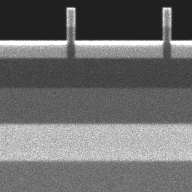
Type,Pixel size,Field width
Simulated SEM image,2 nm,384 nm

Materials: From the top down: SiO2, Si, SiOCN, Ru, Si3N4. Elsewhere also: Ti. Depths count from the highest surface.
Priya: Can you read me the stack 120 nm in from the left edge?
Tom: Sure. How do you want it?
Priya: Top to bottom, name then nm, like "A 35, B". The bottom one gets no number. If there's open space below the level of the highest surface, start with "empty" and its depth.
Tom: empty 66, SiO2 34, Si 60, SiOCN 72, Ru 74, Si3N4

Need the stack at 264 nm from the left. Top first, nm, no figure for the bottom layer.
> empty 66, SiO2 34, Si 60, SiOCN 72, Ru 74, Si3N4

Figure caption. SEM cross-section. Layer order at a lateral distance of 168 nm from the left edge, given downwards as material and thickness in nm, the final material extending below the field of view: empty 66, SiO2 34, Si 60, SiOCN 72, Ru 74, Si3N4